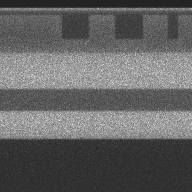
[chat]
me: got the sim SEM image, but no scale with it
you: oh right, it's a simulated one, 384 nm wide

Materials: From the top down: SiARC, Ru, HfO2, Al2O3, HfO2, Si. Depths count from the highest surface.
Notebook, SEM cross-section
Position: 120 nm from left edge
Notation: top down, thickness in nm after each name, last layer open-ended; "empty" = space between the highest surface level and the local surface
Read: SiARC 14, Ru 76, HfO2 72, Al2O3 44, HfO2 56, Si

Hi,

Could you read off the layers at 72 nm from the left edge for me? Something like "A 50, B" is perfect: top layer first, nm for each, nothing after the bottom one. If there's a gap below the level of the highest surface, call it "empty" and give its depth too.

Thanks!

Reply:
SiARC 14, Ru 76, HfO2 72, Al2O3 44, HfO2 56, Si